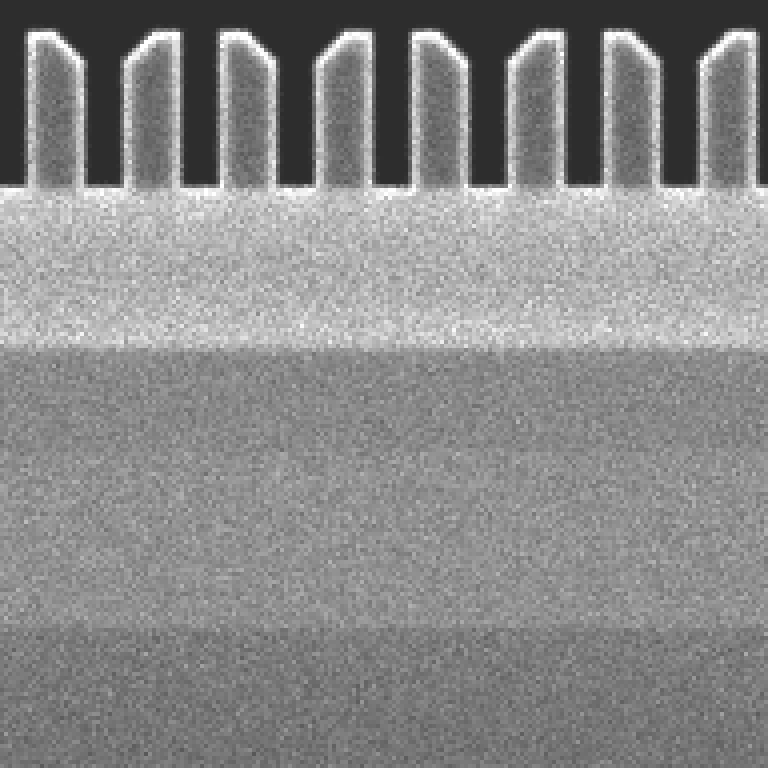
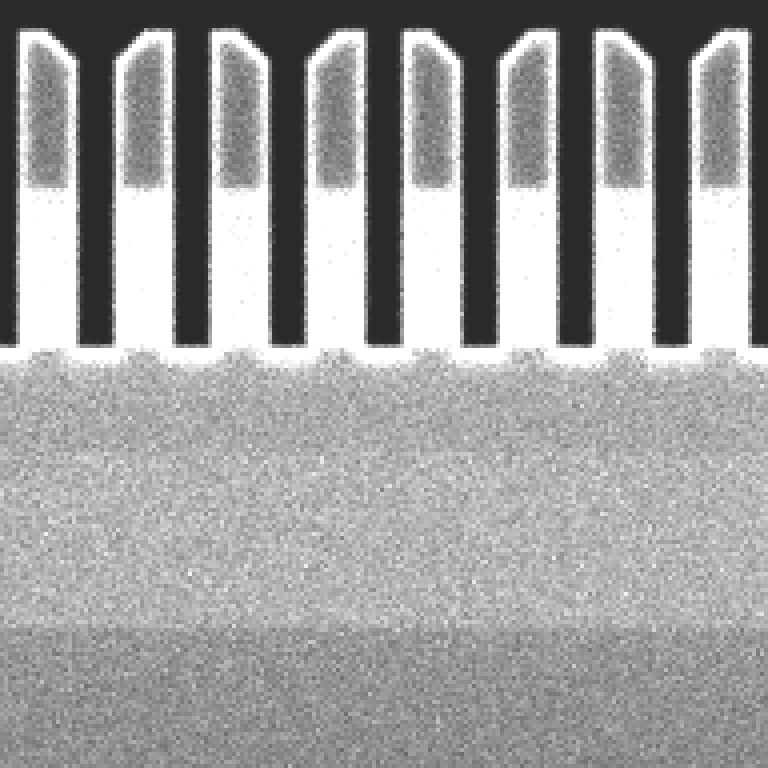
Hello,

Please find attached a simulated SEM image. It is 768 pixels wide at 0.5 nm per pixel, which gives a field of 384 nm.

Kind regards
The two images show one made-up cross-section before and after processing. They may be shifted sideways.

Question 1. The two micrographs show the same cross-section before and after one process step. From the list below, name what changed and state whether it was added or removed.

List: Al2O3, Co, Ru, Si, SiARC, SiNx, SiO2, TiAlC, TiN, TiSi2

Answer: Ru, removed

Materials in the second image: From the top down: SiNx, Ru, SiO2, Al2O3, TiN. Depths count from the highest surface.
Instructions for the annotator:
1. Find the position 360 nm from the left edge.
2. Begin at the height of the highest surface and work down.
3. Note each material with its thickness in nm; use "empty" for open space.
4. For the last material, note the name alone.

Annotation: SiNx 78, Ru 80, SiO2 52, Al2O3 88, TiN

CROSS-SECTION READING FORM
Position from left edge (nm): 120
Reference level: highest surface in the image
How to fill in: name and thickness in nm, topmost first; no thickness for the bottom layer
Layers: empty 2, SiNx 76, Ru 80, SiO2 52, Al2O3 88, TiN